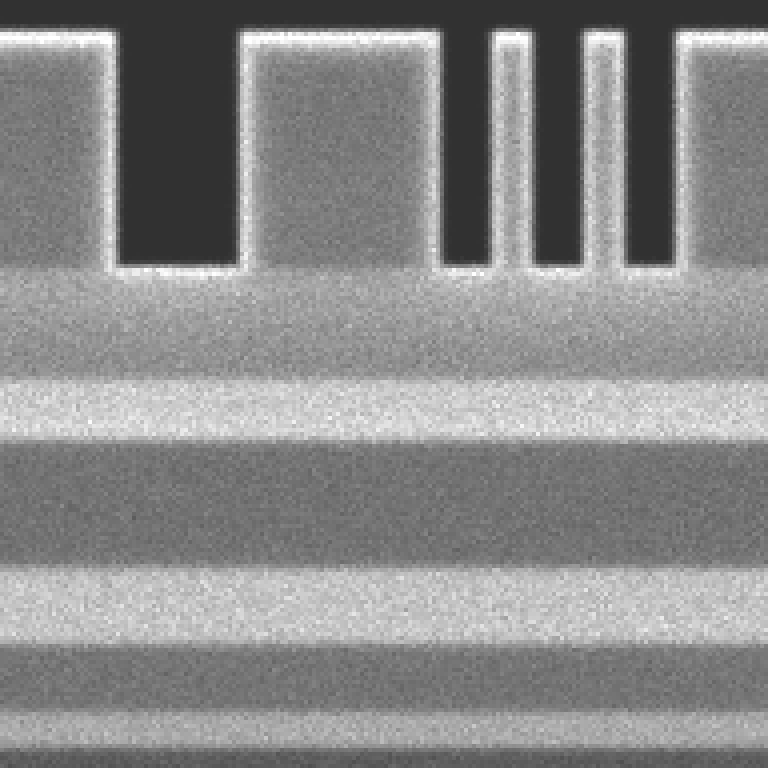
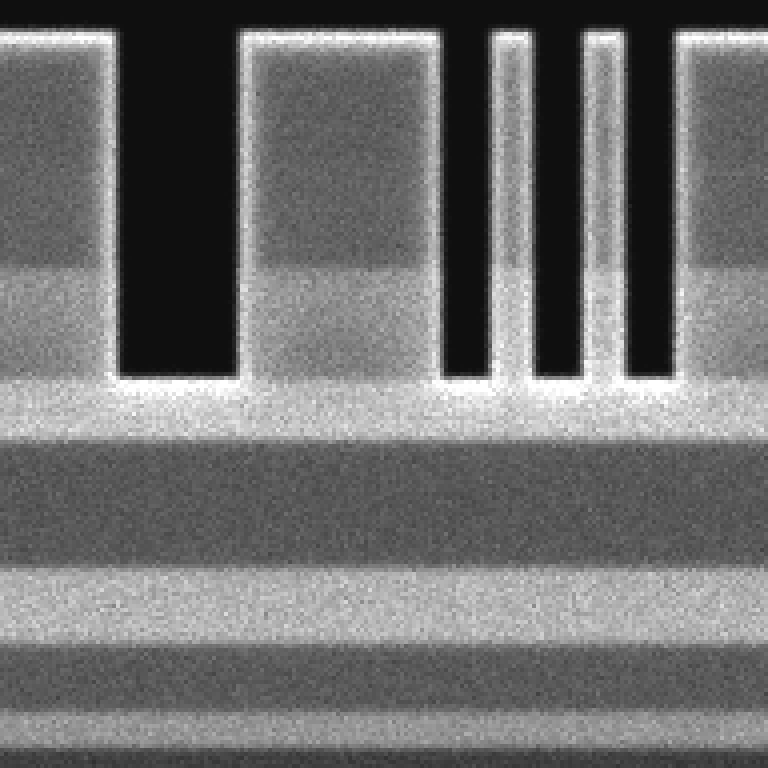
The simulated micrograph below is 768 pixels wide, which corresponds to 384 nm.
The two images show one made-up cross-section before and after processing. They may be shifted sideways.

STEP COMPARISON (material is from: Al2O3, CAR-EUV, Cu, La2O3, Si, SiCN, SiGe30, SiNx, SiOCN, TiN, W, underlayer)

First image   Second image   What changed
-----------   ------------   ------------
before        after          TiN, removed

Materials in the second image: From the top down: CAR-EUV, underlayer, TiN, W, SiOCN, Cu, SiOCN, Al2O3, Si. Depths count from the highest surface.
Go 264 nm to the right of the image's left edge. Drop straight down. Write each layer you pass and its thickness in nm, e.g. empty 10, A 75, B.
CAR-EUV 66, underlayer 52, TiN 56, W 30, SiOCN 64, Cu 38, SiOCN 34, Al2O3 18, Si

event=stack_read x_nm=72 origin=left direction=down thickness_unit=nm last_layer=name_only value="empty 174, W 30, SiOCN 64, Cu 38, SiOCN 34, Al2O3 18, Si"